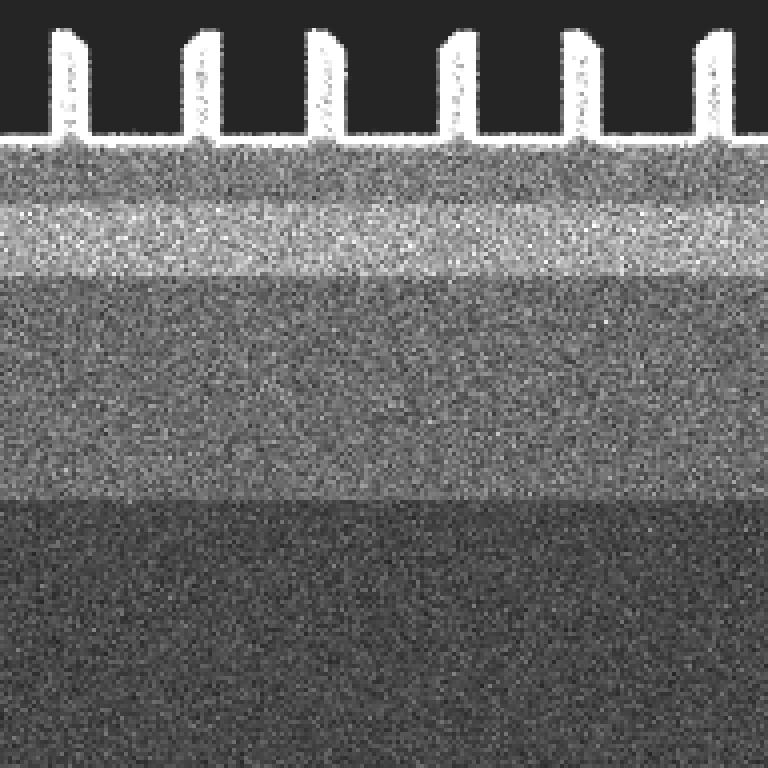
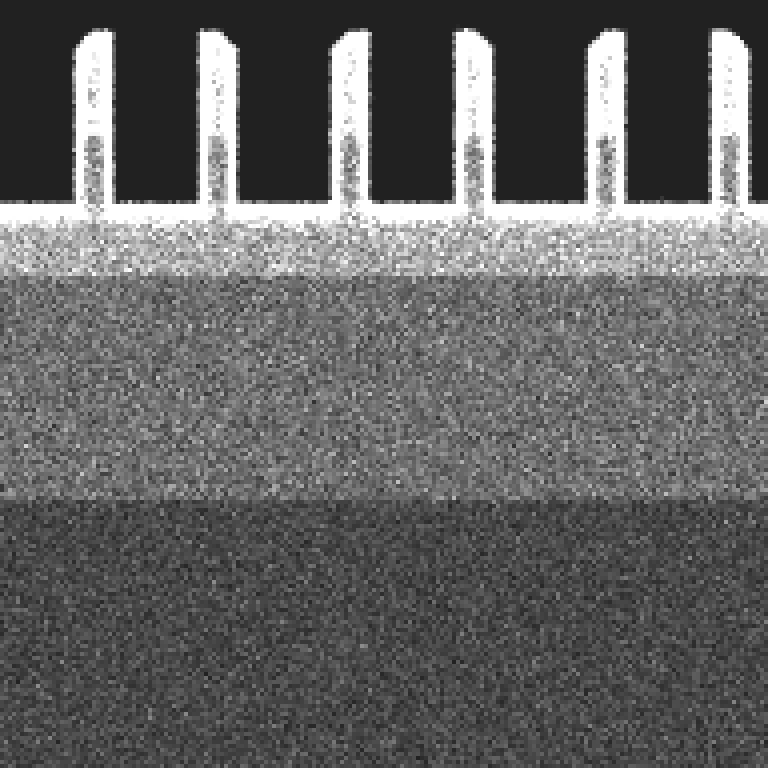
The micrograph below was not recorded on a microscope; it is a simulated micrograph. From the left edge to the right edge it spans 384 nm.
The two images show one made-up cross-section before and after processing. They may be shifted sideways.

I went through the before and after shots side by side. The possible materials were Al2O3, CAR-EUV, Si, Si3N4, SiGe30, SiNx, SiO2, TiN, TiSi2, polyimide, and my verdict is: removed, Si3N4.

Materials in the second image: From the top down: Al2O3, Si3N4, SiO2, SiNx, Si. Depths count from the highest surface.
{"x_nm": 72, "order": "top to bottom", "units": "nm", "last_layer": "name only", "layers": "empty 86, SiO2 36, SiNx 112, Si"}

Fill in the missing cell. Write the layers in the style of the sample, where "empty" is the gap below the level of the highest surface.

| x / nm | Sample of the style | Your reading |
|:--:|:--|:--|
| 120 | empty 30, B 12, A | empty 86, SiO2 36, SiNx 112, Si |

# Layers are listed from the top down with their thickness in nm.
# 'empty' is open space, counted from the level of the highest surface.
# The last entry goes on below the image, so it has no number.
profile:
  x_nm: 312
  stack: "empty 86, SiO2 36, SiNx 112, Si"